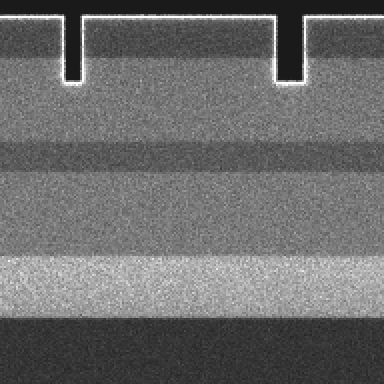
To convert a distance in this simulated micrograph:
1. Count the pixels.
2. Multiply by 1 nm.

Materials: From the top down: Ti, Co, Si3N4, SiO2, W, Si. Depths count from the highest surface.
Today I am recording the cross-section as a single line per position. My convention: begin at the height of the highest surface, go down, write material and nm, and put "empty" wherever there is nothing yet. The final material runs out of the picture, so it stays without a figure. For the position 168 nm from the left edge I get Ti 42, Co 84, Si3N4 30, SiO2 84, W 62, Si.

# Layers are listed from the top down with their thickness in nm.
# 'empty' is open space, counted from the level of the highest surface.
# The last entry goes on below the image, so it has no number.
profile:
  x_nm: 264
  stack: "Ti 42, Co 84, Si3N4 30, SiO2 84, W 62, Si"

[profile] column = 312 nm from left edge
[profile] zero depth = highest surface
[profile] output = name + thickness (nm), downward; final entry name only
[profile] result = Ti 42, Co 84, Si3N4 30, SiO2 84, W 62, Si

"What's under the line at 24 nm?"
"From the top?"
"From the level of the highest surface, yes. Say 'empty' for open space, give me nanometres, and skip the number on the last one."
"Ti 42, Co 84, Si3N4 30, SiO2 84, W 62, Si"